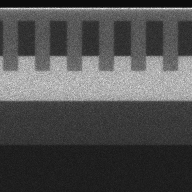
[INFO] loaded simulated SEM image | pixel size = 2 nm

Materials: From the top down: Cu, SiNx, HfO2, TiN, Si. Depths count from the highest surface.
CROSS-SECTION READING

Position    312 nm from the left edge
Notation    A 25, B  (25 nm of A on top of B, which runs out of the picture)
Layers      Cu 26, SiNx 70, HfO2 90, TiN 88, Si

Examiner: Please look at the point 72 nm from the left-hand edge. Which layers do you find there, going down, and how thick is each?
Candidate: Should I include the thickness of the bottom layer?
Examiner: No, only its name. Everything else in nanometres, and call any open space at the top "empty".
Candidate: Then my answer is Cu 126, HfO2 60, TiN 88, Si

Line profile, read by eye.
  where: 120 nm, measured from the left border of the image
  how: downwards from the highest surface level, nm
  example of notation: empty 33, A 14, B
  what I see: Cu 26, SiNx 70, HfO2 90, TiN 88, Si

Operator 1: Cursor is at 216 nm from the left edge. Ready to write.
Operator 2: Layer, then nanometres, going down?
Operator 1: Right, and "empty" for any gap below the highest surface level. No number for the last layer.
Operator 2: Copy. Cu 126, HfO2 60, TiN 88, Si